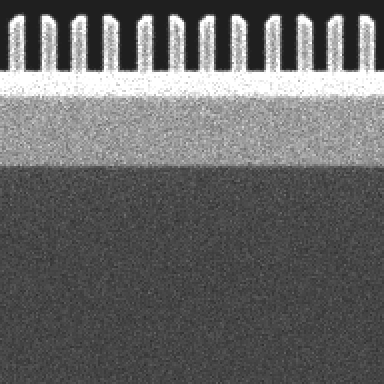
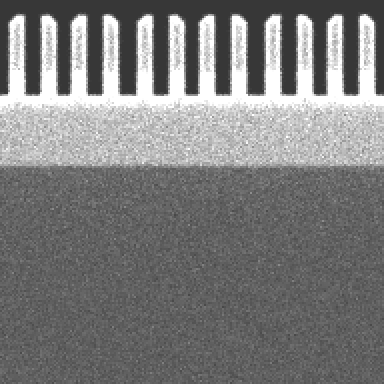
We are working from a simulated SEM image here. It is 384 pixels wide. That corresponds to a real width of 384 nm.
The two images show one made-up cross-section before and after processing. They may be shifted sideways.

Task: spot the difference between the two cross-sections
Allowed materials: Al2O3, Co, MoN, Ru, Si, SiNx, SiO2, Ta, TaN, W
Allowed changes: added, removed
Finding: removed Ru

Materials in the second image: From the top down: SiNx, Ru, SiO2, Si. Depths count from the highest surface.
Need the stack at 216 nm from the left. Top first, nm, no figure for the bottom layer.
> empty 80, SiO2 70, Si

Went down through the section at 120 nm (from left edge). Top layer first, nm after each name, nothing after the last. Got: empty 80, SiO2 70, Si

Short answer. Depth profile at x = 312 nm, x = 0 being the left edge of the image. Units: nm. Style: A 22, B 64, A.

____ empty 80, SiO2 70, Si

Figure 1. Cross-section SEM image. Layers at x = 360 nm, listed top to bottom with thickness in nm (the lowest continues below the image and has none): SiNx 56, Ru 24, SiO2 70, Si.